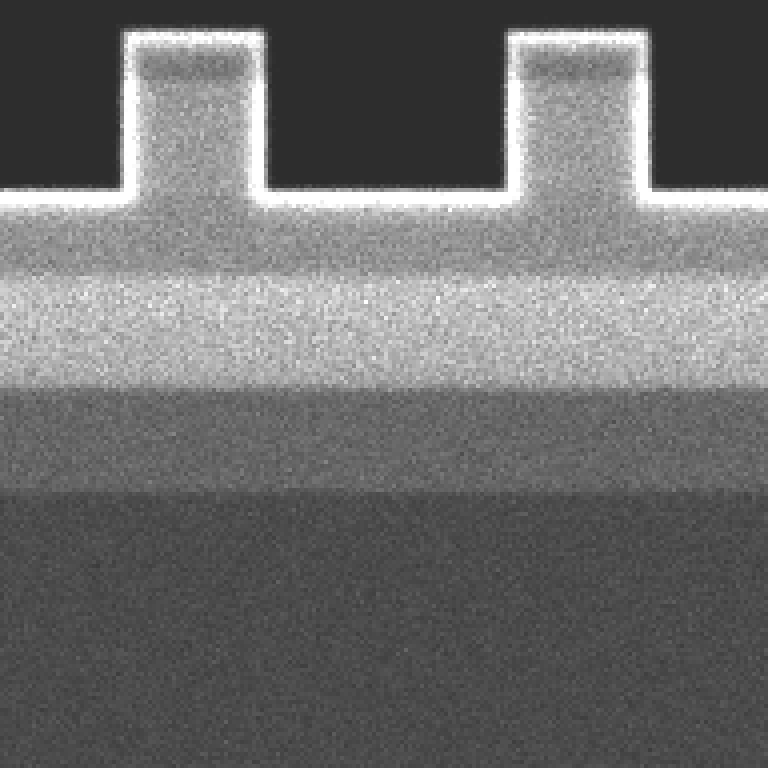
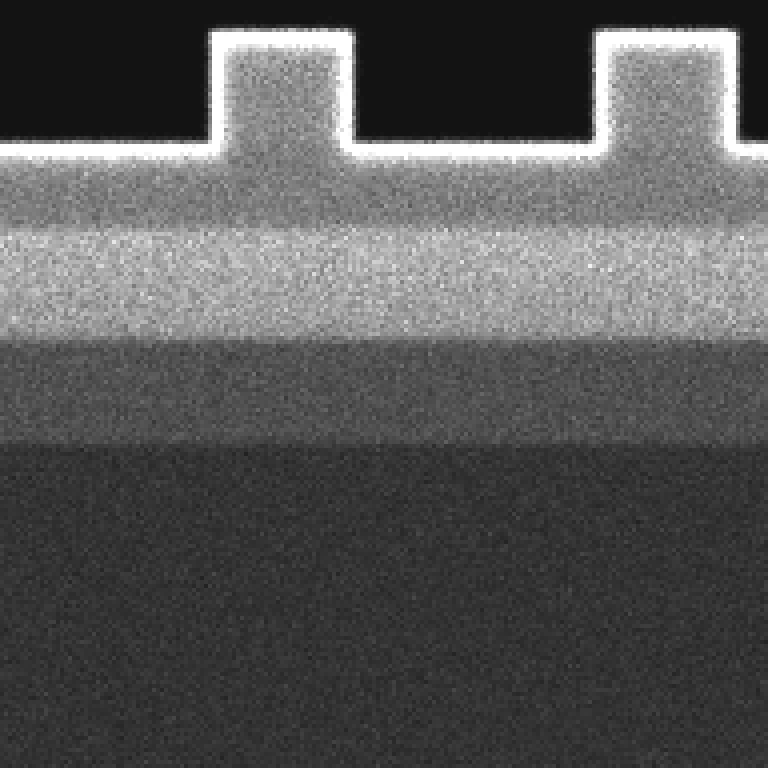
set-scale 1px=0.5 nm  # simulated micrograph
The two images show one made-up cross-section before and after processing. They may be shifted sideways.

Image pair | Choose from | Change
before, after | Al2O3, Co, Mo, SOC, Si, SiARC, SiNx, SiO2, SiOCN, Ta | SOC (removed)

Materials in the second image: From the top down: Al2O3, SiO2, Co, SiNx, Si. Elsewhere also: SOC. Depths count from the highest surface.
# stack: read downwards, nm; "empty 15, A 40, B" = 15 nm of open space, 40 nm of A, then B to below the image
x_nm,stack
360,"Al2O3 56, SiO2 42, Co 56, SiNx 52, Si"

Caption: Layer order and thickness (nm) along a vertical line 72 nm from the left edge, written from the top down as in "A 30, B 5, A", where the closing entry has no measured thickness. empty 56, SiO2 42, Co 56, SiNx 52, Si